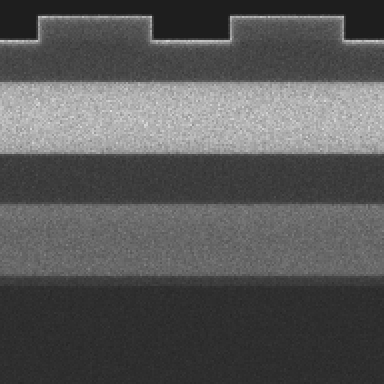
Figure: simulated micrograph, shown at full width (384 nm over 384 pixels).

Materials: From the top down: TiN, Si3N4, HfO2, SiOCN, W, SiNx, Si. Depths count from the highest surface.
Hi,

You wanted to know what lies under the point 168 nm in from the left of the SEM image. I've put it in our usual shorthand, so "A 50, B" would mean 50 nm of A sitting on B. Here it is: empty 24, Si3N4 42, HfO2 72, SiOCN 50, W 72, SiNx 10, Si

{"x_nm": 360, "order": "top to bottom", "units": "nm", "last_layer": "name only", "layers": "empty 24, Si3N4 42, HfO2 72, SiOCN 50, W 72, SiNx 10, Si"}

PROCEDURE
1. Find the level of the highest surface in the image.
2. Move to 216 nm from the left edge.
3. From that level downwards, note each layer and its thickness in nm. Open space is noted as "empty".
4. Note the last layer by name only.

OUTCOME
empty 24, Si3N4 42, HfO2 72, SiOCN 50, W 72, SiNx 10, Si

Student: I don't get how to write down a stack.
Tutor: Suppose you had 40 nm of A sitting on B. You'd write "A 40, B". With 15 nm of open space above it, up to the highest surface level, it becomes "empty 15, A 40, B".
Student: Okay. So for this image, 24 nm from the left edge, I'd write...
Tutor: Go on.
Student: empty 24, Si3N4 42, HfO2 72, SiOCN 50, W 72, SiNx 10, Si